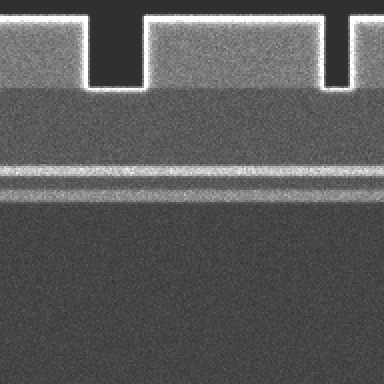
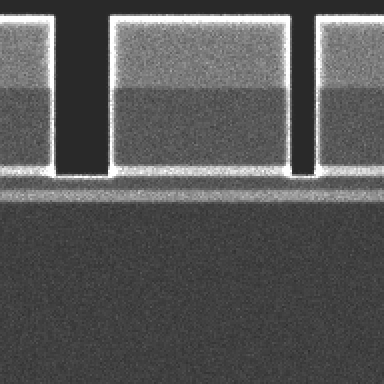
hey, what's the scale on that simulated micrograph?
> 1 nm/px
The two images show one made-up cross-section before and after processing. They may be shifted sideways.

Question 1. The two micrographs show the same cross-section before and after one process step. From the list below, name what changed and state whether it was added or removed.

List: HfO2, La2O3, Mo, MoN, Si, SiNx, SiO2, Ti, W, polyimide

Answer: HfO2 and SiNx, removed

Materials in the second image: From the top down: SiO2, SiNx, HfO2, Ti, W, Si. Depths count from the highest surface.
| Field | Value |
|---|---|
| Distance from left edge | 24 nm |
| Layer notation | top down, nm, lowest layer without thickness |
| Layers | SiO2 72, SiNx 78, HfO2 10, Ti 14, W 12, Si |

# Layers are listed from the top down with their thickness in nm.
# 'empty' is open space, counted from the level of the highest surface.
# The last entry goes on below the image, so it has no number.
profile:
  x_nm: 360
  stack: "SiO2 72, SiNx 78, HfO2 10, Ti 14, W 12, Si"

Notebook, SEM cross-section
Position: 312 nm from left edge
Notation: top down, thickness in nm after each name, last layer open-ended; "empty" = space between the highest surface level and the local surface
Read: empty 160, Ti 14, W 12, Si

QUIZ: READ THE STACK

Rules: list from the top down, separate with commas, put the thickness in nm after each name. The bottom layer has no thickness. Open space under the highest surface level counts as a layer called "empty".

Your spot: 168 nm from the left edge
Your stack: SiO2 72, SiNx 78, HfO2 10, Ti 14, W 12, Si